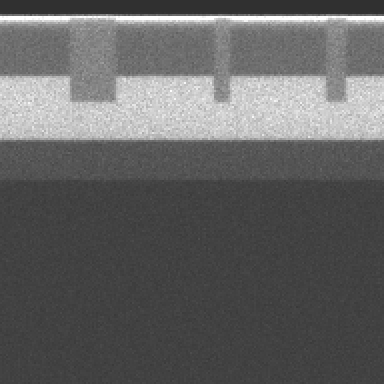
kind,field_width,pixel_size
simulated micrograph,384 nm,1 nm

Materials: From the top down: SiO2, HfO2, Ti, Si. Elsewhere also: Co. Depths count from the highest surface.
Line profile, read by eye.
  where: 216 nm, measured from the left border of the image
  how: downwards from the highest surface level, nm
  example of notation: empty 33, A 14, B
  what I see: Co 86, HfO2 38, Ti 40, Si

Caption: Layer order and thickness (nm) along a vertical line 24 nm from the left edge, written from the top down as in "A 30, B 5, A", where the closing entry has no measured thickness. SiO2 60, HfO2 64, Ti 40, Si